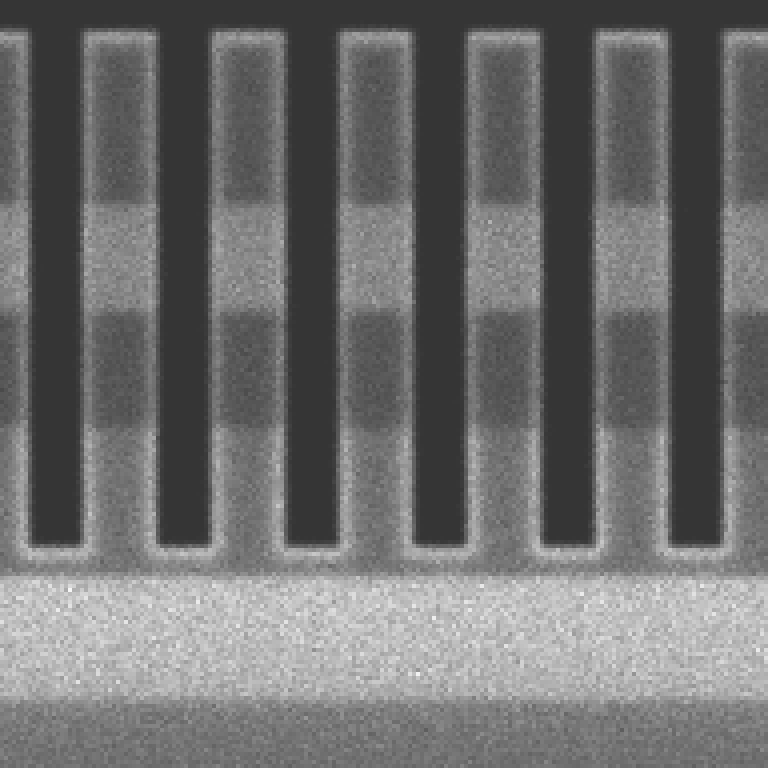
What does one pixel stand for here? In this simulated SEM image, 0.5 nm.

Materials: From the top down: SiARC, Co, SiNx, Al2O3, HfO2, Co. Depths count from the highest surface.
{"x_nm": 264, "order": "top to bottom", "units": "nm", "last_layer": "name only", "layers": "SiARC 86, Co 54, SiNx 58, Al2O3 74, HfO2 62, Co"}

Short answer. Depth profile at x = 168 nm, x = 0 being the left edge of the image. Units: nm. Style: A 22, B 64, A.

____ empty 258, Al2O3 14, HfO2 62, Co